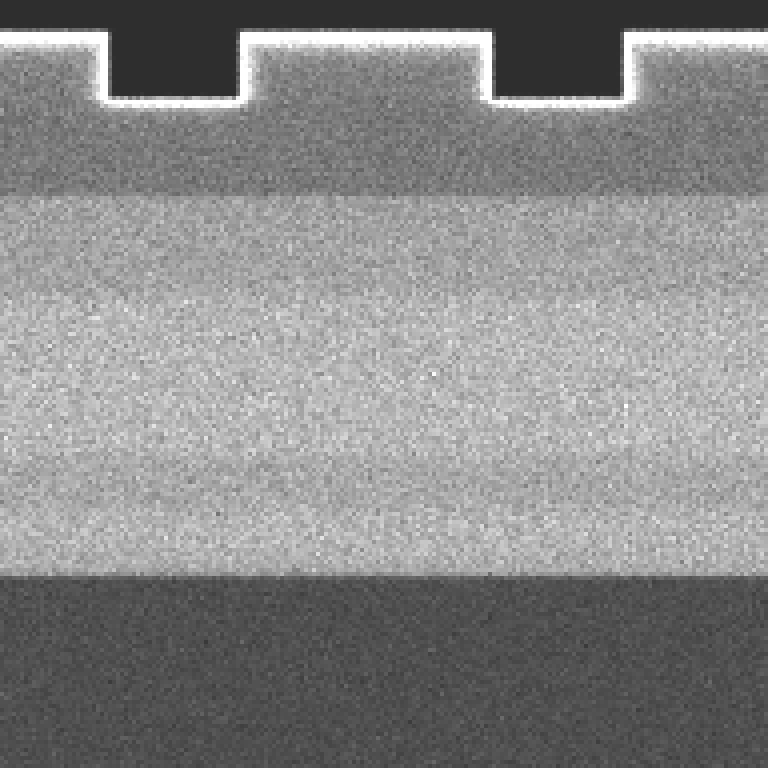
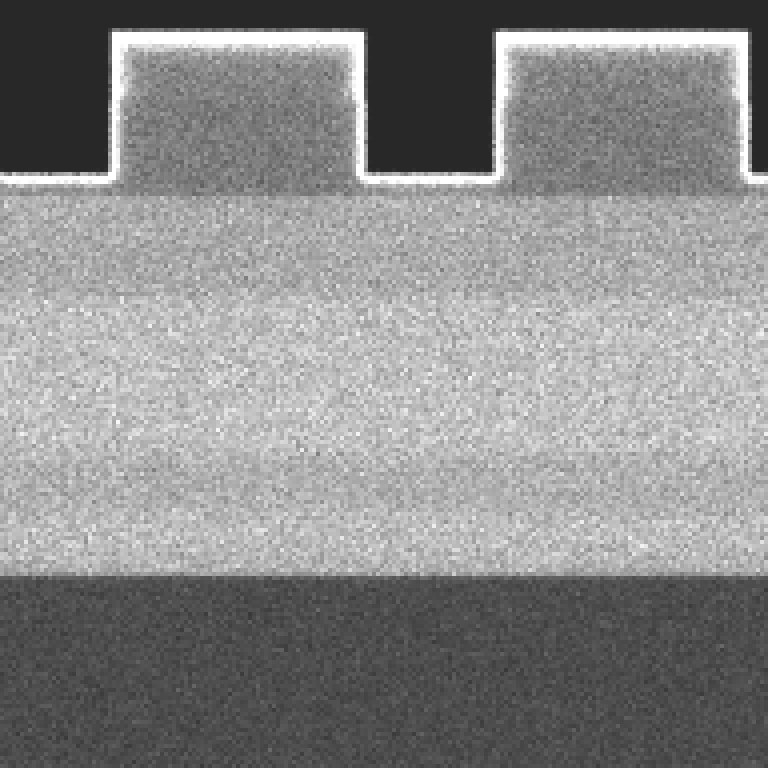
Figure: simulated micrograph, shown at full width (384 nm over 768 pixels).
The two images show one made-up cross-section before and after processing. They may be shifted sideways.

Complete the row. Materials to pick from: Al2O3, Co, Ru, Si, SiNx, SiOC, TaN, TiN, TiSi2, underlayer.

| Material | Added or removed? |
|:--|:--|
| TiN | removed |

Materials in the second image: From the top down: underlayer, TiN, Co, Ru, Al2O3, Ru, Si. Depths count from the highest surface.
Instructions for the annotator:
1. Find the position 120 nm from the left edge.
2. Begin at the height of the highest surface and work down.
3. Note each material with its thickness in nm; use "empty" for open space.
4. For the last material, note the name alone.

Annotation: underlayer 34, TiN 48, Co 50, Ru 80, Al2O3 28, Ru 32, Si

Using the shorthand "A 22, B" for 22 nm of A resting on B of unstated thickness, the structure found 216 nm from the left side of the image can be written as empty 72, TiN 10, Co 50, Ru 80, Al2O3 28, Ru 32, Si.